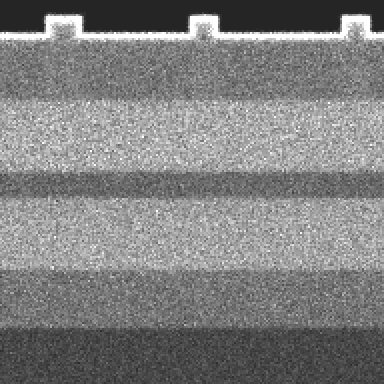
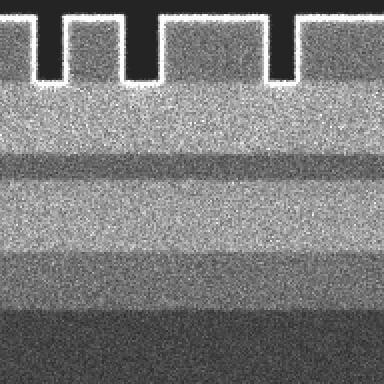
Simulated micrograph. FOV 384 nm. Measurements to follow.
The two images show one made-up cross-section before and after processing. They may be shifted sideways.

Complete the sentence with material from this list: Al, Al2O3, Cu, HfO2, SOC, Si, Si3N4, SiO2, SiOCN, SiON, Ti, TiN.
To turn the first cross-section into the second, SOC must be removed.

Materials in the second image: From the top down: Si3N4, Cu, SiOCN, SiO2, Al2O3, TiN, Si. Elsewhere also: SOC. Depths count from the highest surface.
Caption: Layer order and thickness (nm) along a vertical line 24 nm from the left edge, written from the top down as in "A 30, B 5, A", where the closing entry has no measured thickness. Si3N4 66, Cu 72, SiOCN 26, SiO2 18, Al2O3 54, TiN 58, Si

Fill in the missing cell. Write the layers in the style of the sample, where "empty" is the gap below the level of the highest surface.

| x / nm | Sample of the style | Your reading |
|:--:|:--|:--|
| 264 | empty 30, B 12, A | Si3N4 66, Cu 72, SiOCN 26, SiO2 18, Al2O3 54, TiN 58, Si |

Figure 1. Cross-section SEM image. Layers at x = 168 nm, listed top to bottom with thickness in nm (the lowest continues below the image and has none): Si3N4 66, Cu 72, SiOCN 26, SiO2 18, Al2O3 54, TiN 58, Si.